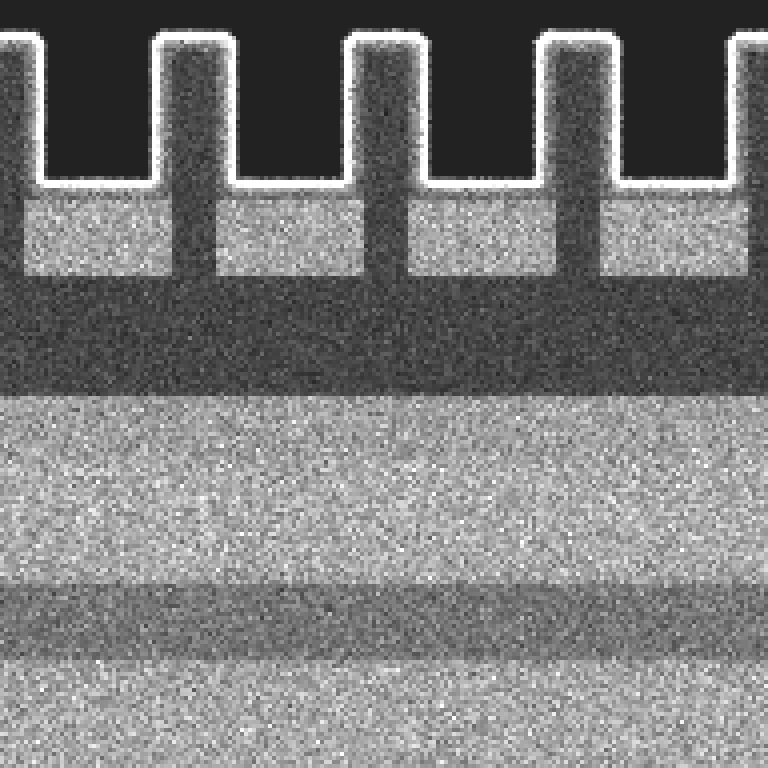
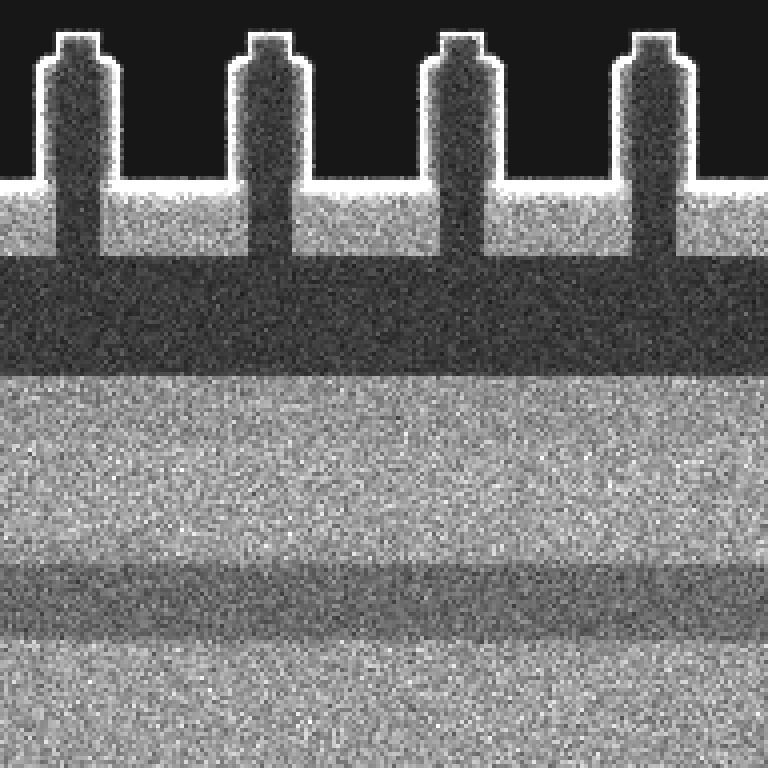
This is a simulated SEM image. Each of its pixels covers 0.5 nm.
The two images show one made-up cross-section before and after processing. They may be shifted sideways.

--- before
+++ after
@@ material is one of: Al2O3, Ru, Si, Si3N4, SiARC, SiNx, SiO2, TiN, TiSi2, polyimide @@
SiNx removed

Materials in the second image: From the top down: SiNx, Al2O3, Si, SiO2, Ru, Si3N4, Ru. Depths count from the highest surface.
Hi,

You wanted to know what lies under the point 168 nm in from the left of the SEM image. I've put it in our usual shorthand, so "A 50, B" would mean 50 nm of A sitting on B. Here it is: empty 74, Al2O3 38, Si 60, SiO2 32, Ru 62, Si3N4 38, Ru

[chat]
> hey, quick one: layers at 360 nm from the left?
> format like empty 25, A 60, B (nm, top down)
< empty 74, Al2O3 38, Si 60, SiO2 32, Ru 62, Si3N4 38, Ru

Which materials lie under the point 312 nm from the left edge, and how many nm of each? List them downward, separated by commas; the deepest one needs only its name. empty 12, SiNx 62, Al2O3 38, Si 60, SiO2 32, Ru 62, Si3N4 38, Ru